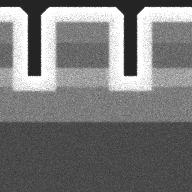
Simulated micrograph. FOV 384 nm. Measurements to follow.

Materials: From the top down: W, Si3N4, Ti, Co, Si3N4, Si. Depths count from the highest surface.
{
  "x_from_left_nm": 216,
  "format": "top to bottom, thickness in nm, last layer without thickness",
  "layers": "W 28, Si3N4 42, Ti 50, Co 38, Si3N4 70, Si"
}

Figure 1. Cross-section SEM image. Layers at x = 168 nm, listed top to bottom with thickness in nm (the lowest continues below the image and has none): W 28, Si3N4 42, Ti 50, Co 38, Si3N4 70, Si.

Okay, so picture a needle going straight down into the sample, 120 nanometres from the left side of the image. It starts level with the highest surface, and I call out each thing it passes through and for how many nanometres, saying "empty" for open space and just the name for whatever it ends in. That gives W 28, Si3N4 42, Ti 50, Co 38, Si3N4 70, Si